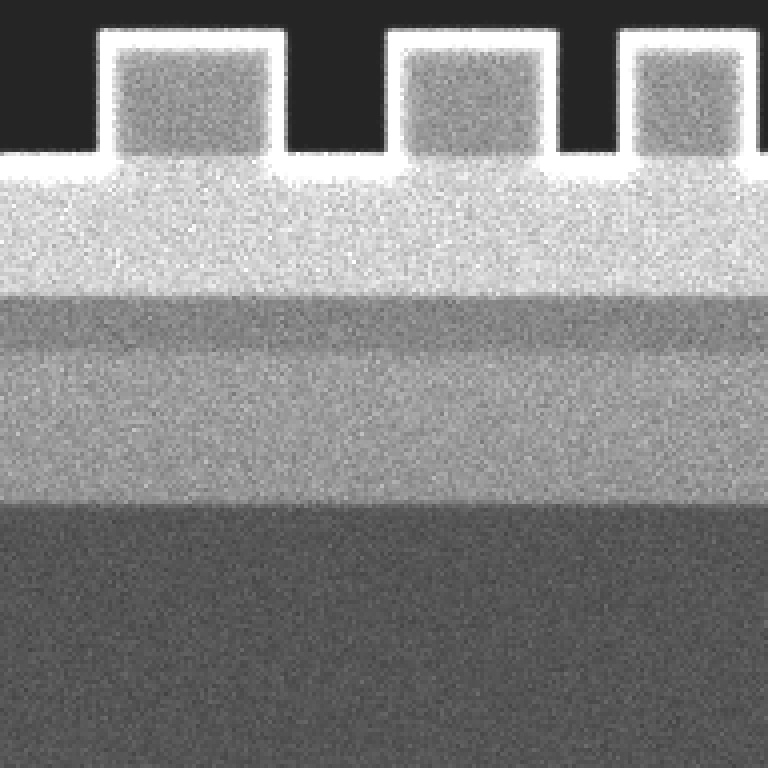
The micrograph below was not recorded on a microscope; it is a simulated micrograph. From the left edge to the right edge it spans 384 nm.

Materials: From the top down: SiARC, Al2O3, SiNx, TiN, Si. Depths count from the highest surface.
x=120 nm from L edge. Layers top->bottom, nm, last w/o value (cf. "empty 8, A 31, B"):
SiARC 62, Al2O3 70, SiNx 28, TiN 76, Si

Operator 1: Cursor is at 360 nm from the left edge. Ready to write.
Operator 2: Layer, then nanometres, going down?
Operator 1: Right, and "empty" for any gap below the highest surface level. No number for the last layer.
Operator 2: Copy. SiARC 62, Al2O3 70, SiNx 28, TiN 76, Si